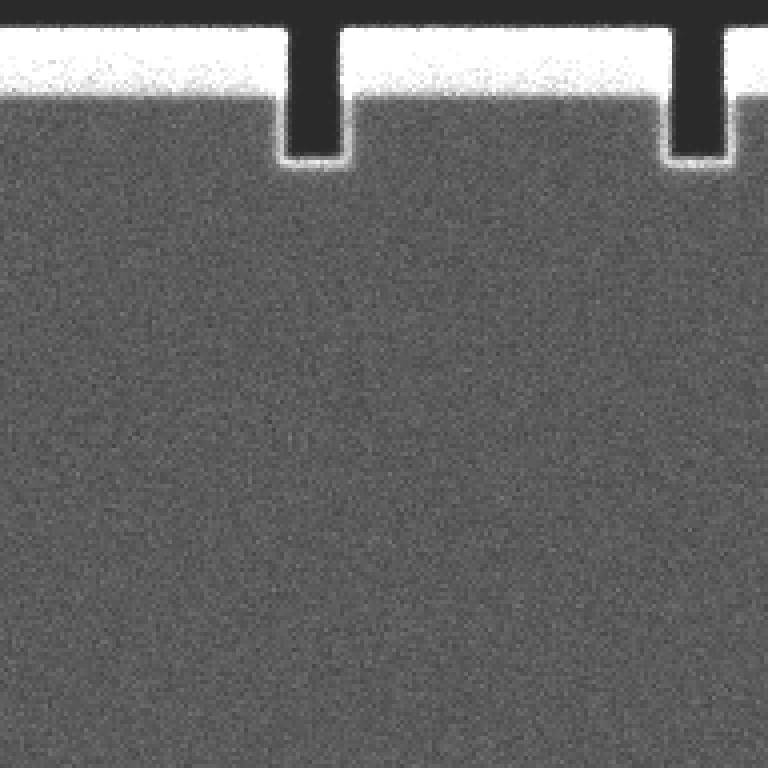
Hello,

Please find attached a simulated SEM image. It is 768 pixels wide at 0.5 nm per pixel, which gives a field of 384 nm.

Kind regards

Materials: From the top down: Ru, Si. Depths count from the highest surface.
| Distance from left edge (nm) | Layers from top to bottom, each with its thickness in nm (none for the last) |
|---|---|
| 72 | Ru 32, Si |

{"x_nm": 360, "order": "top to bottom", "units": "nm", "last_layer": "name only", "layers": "empty 64, Si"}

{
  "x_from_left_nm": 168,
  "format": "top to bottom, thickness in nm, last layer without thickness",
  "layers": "empty 64, Si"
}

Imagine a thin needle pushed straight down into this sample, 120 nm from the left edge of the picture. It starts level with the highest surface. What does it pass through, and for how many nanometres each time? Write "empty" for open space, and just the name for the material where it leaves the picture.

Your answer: Ru 32, Si